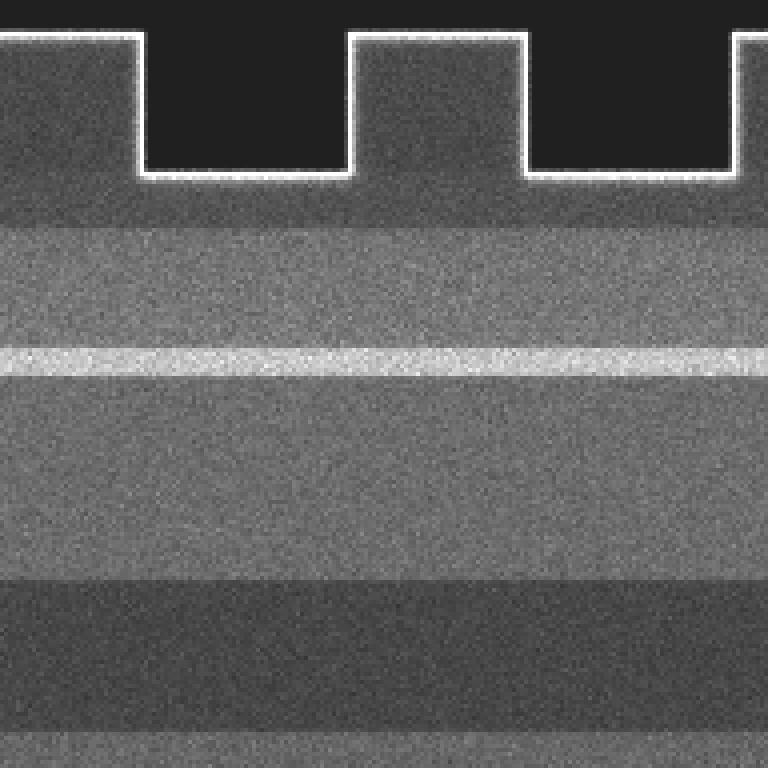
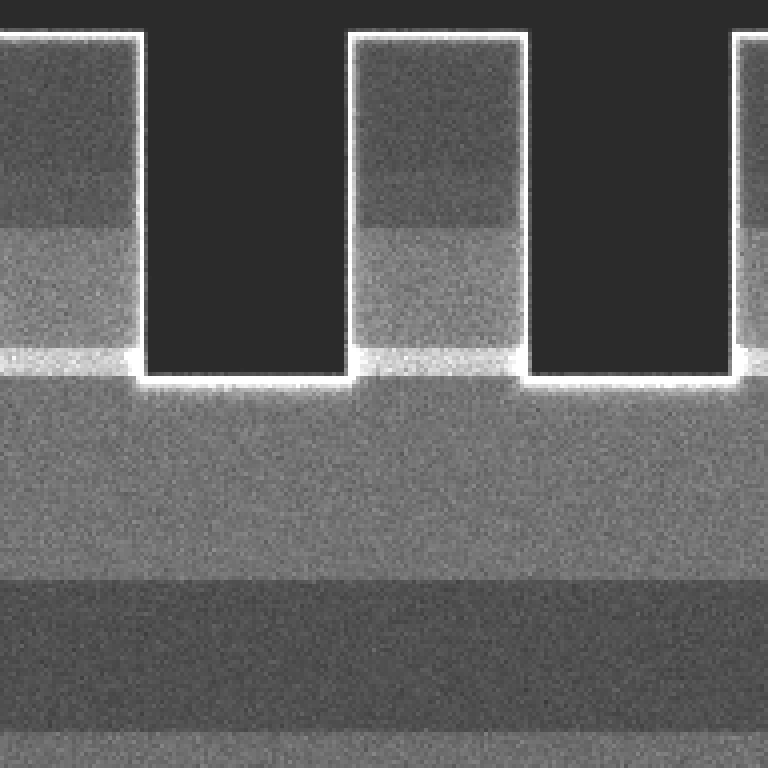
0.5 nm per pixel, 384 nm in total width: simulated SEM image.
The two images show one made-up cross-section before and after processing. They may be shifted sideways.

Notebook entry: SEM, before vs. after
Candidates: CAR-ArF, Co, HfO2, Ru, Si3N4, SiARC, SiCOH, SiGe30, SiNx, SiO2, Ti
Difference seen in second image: HfO2 and Ru and Si3N4 removed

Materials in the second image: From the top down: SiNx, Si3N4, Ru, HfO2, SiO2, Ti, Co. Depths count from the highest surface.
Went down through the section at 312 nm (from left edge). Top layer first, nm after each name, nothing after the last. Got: empty 172, SiO2 102, Ti 76, Co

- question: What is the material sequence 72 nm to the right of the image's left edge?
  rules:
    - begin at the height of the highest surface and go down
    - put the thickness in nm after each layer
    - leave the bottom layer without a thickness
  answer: empty 172, SiO2 102, Ti 76, Co